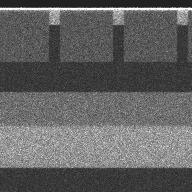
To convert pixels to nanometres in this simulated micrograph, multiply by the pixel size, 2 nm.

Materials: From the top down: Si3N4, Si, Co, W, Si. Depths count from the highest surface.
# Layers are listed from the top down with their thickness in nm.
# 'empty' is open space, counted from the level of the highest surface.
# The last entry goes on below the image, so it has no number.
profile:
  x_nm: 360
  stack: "W 34, Si 134, Co 68, W 84, Si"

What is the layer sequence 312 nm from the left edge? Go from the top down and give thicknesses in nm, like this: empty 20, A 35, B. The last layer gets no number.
Si3N4 108, Si 60, Co 68, W 84, Si